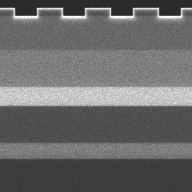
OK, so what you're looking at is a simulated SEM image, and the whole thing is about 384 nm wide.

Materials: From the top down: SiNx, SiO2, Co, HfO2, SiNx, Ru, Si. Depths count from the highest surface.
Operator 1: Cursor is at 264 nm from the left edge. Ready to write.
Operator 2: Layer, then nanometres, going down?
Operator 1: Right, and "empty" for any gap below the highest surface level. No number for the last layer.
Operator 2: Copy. empty 16, SiO2 68, Co 74, HfO2 38, SiNx 74, Ru 32, Si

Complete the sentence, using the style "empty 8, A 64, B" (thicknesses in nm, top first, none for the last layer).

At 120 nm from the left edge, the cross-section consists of SiNx 16, SiO2 68, Co 74, HfO2 38, SiNx 74, Ru 32, Si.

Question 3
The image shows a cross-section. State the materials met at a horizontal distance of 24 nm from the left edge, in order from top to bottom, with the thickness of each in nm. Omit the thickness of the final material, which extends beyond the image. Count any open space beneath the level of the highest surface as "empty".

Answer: SiNx 16, SiO2 68, Co 74, HfO2 38, SiNx 74, Ru 32, Si